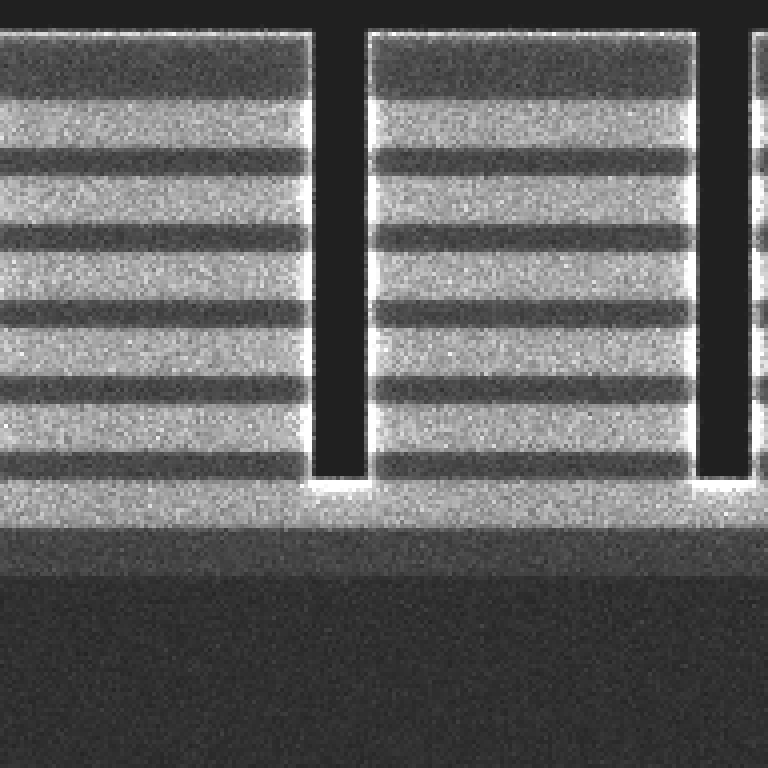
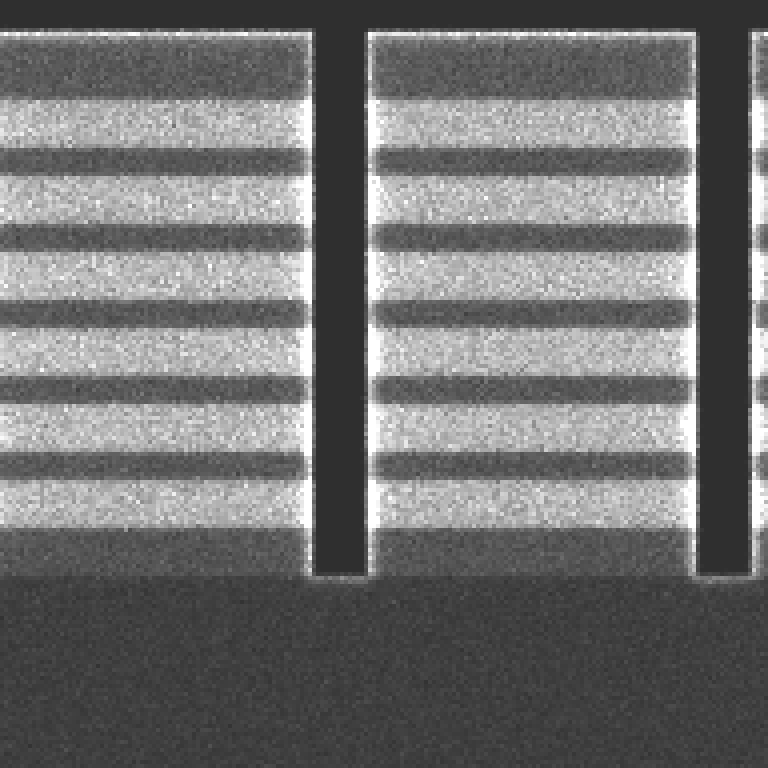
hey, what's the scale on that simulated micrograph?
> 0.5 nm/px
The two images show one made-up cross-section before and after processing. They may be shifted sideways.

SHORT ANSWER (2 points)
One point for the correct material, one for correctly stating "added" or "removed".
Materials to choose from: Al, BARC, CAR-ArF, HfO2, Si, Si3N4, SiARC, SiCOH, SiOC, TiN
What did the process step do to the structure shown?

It removed HfO2 and Si3N4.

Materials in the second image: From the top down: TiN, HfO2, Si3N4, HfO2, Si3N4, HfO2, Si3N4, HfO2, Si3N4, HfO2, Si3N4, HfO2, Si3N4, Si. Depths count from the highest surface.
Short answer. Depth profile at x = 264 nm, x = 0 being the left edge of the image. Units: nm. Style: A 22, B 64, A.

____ TiN 34, HfO2 24, Si3N4 14, HfO2 24, Si3N4 14, HfO2 24, Si3N4 14, HfO2 24, Si3N4 14, HfO2 24, Si3N4 14, HfO2 24, Si3N4 24, Si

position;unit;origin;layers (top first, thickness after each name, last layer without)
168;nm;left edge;empty 272, Si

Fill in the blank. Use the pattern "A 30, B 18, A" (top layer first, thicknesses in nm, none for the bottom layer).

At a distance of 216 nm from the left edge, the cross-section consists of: TiN 34, HfO2 24, Si3N4 14, HfO2 24, Si3N4 14, HfO2 24, Si3N4 14, HfO2 24, Si3N4 14, HfO2 24, Si3N4 14, HfO2 24, Si3N4 24, Si